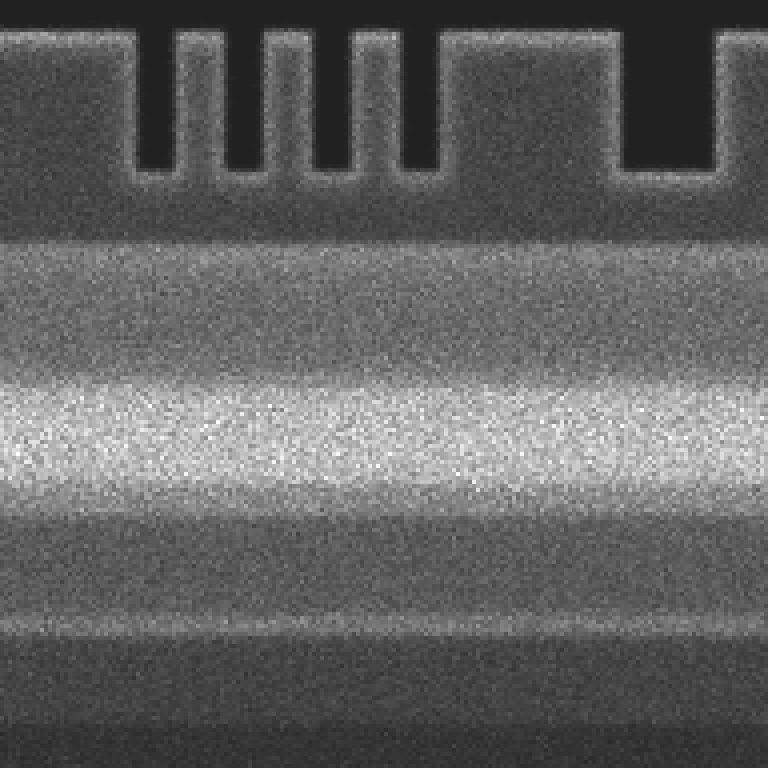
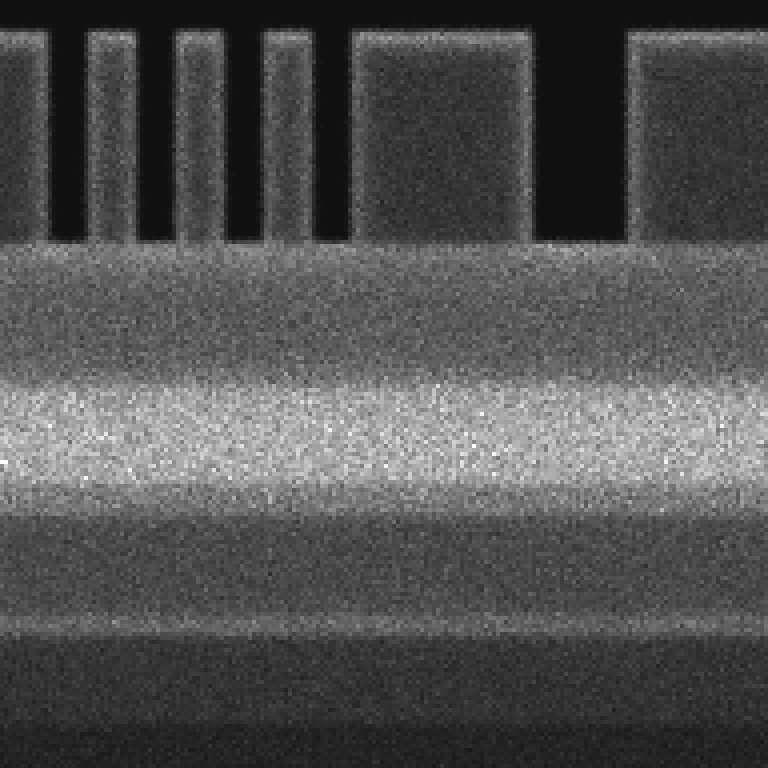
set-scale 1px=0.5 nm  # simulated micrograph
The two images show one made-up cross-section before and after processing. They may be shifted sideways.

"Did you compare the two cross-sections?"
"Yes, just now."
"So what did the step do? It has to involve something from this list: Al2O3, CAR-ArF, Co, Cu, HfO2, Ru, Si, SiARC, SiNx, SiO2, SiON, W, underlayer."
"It removed underlayer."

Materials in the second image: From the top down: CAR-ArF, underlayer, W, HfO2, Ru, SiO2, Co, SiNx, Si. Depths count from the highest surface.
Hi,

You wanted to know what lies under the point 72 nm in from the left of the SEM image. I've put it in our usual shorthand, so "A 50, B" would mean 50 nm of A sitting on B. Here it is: empty 106, W 72, HfO2 48, Ru 16, SiO2 50, Co 10, SiNx 44, Si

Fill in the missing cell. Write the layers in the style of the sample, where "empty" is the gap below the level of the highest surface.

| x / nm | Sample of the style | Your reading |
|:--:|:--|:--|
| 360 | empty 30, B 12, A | CAR-ArF 70, underlayer 36, W 72, HfO2 48, Ru 16, SiO2 50, Co 10, SiNx 44, Si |